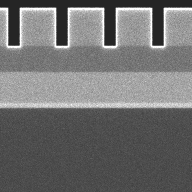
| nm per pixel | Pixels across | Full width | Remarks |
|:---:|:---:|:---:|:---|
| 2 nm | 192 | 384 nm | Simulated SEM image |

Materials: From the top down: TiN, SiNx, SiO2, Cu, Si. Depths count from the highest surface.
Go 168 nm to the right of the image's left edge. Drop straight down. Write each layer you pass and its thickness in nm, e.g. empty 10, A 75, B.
TiN 76, SiNx 52, SiO2 62, Cu 10, Si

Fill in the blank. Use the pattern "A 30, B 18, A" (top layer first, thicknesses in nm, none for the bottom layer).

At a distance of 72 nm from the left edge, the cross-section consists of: TiN 76, SiNx 52, SiO2 62, Cu 10, Si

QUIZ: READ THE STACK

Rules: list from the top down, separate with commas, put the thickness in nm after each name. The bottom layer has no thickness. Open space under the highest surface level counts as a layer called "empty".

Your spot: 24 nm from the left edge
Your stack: empty 76, SiNx 52, SiO2 62, Cu 10, Si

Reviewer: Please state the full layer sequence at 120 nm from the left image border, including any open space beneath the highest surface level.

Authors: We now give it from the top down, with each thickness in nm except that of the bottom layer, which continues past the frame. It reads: empty 76, SiNx 52, SiO2 62, Cu 10, Si